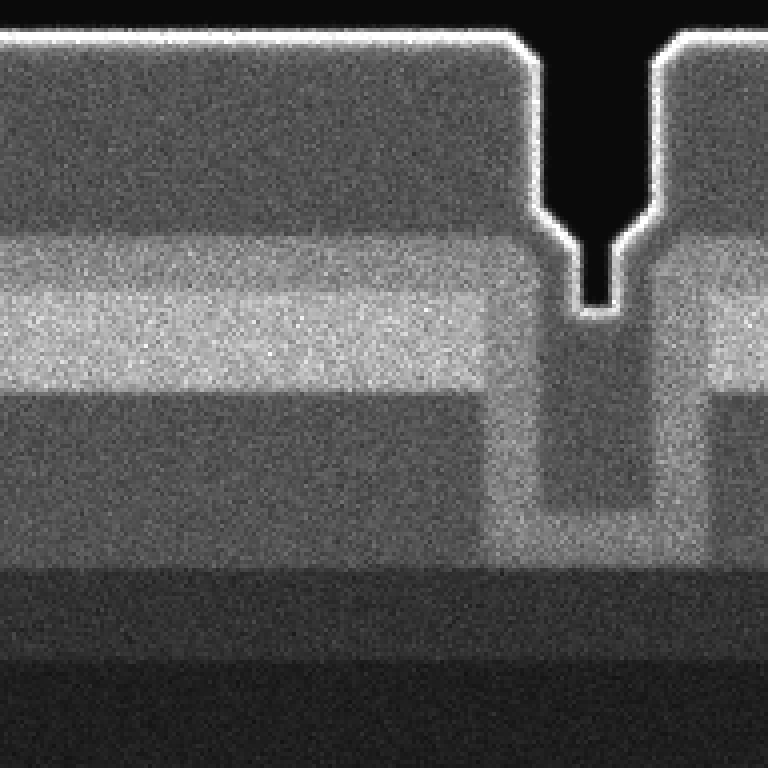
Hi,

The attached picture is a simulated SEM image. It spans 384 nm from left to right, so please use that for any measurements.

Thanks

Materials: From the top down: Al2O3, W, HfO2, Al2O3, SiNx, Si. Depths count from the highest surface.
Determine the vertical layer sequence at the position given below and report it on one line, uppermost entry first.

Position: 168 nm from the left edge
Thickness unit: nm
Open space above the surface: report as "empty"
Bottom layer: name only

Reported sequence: Al2O3 102, W 28, HfO2 50, Al2O3 88, SiNx 46, Si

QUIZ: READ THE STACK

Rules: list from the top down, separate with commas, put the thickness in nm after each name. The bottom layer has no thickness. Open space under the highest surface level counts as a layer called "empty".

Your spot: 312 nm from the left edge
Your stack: empty 100, Al2O3 140, W 28, SiNx 46, Si